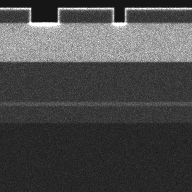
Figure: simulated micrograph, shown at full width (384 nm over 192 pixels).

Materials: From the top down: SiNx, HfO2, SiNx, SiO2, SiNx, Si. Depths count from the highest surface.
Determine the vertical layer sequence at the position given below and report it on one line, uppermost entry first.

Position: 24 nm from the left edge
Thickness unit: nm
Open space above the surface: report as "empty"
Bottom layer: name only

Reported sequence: SiNx 30, HfO2 78, SiNx 80, SiO2 8, SiNx 34, Si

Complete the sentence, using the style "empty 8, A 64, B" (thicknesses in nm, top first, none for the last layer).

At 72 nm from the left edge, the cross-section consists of empty 30, HfO2 78, SiNx 80, SiO2 8, SiNx 34, Si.